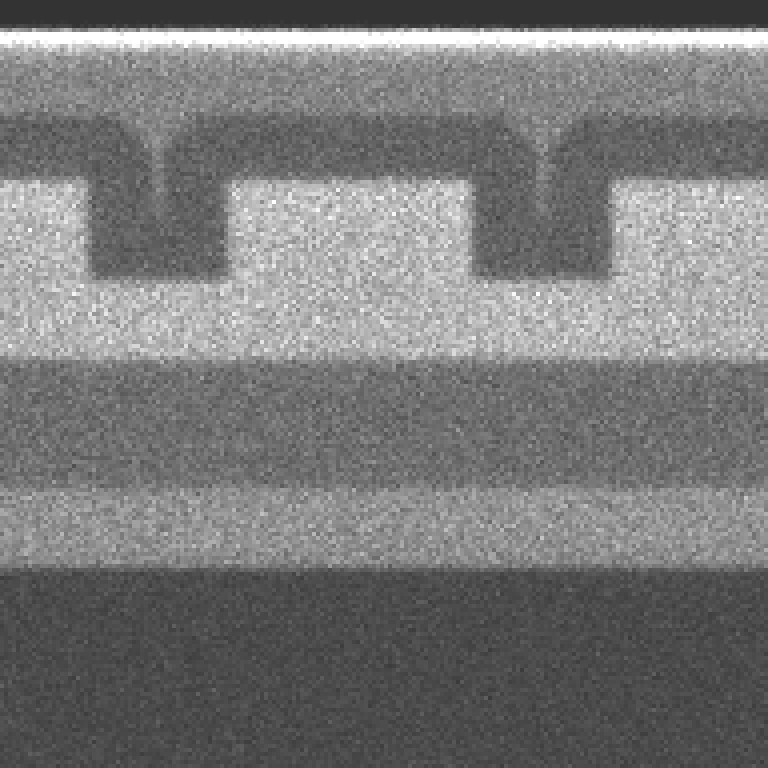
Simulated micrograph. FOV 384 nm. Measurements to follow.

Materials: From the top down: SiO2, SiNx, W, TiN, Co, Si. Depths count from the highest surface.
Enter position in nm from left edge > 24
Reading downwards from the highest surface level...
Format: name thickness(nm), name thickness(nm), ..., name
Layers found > SiO2 42, SiNx 32, W 90, TiN 64, Co 40, Si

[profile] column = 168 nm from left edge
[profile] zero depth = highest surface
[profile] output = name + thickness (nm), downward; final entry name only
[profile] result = SiO2 42, SiNx 32, W 90, TiN 64, Co 40, Si